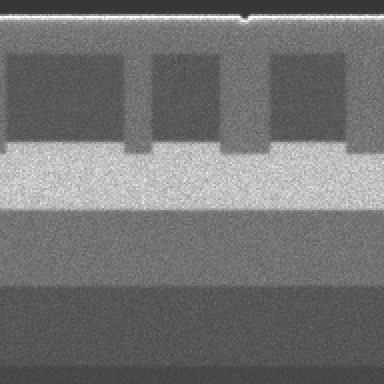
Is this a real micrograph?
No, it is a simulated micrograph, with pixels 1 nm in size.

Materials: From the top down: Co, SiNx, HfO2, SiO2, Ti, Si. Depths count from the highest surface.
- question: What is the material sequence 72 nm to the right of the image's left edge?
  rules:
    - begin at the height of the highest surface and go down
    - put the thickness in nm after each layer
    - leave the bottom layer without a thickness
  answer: Co 38, SiNx 88, HfO2 68, SiO2 76, Ti 80, Si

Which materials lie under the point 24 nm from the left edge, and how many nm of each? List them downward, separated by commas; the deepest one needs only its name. Co 38, SiNx 88, HfO2 68, SiO2 76, Ti 80, Si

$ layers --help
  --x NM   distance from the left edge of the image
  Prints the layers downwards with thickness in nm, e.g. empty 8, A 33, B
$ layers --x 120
Co 38, SiNx 88, HfO2 68, SiO2 76, Ti 80, Si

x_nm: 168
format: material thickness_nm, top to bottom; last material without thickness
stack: Co 38, SiNx 88, HfO2 68, SiO2 76, Ti 80, Si